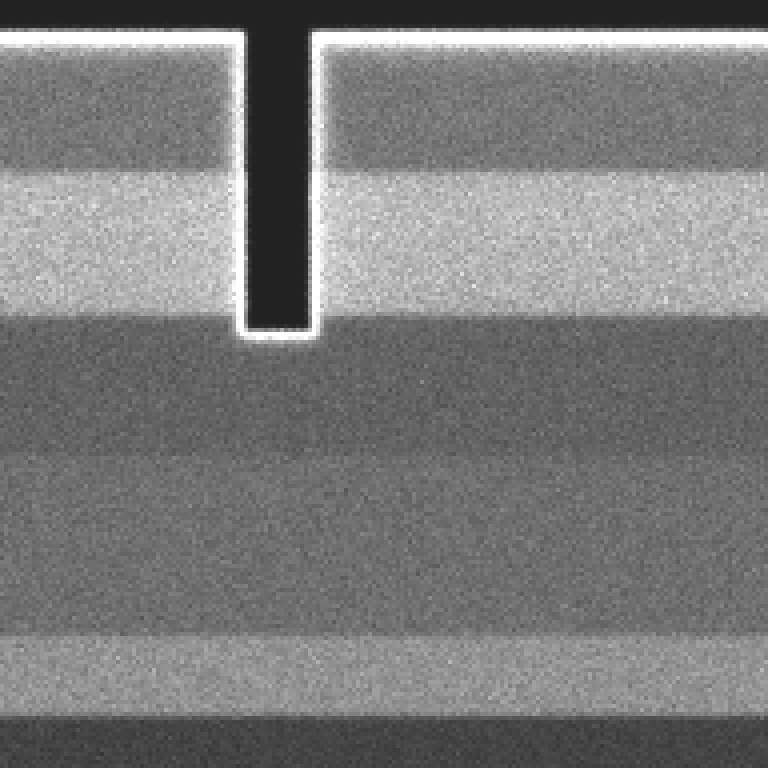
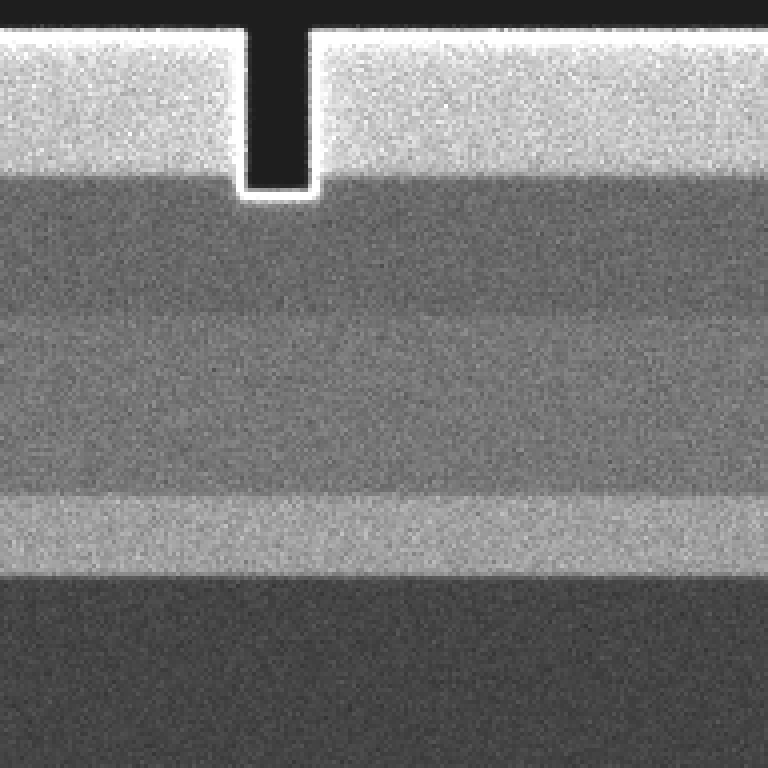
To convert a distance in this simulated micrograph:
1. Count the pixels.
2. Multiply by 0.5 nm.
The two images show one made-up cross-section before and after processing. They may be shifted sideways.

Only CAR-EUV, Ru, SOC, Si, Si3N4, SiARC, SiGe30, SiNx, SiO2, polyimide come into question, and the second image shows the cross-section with SOC removed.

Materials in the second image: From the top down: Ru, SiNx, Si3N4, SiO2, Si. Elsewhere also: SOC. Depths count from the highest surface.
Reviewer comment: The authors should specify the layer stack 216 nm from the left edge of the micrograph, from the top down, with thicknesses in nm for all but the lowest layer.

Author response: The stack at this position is Ru 72, SiNx 70, Si3N4 90, SiO2 40, Si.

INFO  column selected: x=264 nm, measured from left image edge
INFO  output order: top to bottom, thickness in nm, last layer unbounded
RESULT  Ru 72, SiNx 70, Si3N4 90, SiO2 40, Si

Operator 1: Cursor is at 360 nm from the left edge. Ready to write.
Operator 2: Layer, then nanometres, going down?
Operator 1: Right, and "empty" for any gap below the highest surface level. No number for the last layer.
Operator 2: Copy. Ru 72, SiNx 70, Si3N4 90, SiO2 40, Si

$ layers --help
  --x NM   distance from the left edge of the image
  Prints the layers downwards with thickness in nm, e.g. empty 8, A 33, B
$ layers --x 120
Ru 72, SiNx 70, Si3N4 90, SiO2 40, Si